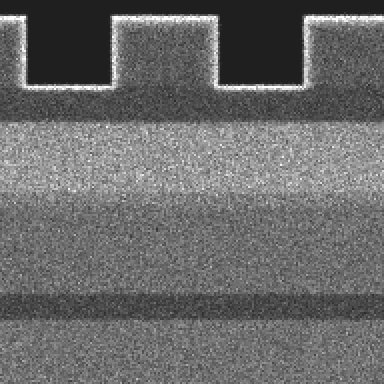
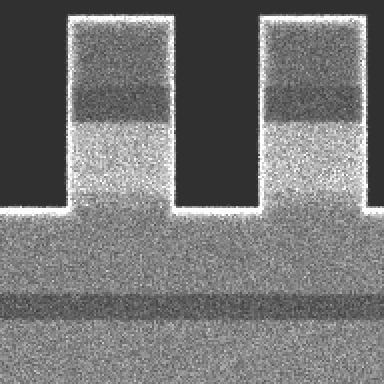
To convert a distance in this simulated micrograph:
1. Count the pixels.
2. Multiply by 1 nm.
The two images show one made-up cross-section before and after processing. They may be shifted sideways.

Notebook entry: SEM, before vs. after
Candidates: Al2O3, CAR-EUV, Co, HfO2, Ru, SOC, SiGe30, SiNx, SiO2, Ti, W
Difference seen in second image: Ru and SiNx and W removed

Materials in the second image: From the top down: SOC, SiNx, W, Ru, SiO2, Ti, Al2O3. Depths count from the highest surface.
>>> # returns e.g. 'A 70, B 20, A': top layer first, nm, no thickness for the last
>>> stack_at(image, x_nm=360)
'SOC 70, SiNx 36, W 70, Ru 16, SiO2 86, Ti 26, Al2O3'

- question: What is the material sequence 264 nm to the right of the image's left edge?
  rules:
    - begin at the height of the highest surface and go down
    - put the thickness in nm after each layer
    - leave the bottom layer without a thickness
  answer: SOC 70, SiNx 36, W 70, Ru 16, SiO2 86, Ti 26, Al2O3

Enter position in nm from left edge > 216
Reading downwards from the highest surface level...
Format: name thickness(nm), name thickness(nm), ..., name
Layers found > empty 192, SiO2 86, Ti 26, Al2O3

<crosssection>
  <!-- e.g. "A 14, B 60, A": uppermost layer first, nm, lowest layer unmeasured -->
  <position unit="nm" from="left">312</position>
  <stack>SOC 70, SiNx 36, W 70, Ru 16, SiO2 86, Ti 26, Al2O3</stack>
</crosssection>